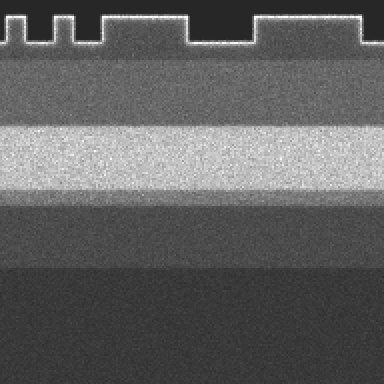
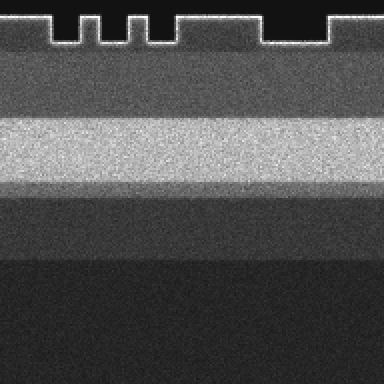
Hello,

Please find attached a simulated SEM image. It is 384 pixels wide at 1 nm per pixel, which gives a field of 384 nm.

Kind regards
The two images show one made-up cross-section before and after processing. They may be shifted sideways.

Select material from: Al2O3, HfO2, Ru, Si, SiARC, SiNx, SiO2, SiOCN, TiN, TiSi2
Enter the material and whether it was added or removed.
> TiN / removed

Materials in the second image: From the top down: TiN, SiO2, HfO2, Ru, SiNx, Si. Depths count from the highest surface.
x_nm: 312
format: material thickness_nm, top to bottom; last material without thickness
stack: empty 26, TiN 10, SiO2 66, HfO2 64, Ru 16, SiNx 62, Si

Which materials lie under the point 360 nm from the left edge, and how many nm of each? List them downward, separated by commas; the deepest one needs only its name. TiN 36, SiO2 66, HfO2 64, Ru 16, SiNx 62, Si